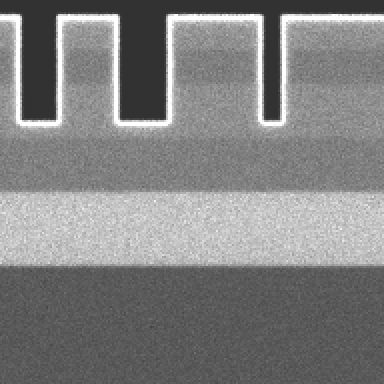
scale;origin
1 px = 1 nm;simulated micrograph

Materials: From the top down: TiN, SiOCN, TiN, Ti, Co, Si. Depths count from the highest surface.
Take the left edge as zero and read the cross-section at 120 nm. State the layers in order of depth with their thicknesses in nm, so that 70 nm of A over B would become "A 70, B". empty 106, TiN 16, Ti 54, Co 74, Si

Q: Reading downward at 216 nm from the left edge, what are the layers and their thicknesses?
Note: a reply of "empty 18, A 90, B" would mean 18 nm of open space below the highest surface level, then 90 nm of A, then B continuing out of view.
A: TiN 34, SiOCN 34, TiN 54, Ti 54, Co 74, Si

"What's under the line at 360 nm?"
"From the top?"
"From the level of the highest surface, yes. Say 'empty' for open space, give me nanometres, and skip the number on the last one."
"TiN 34, SiOCN 34, TiN 54, Ti 54, Co 74, Si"